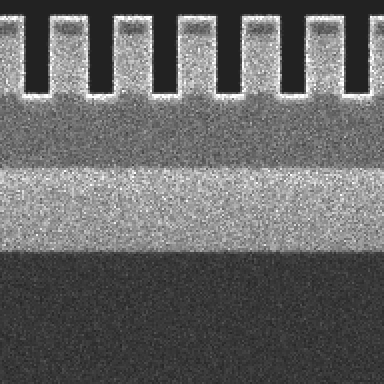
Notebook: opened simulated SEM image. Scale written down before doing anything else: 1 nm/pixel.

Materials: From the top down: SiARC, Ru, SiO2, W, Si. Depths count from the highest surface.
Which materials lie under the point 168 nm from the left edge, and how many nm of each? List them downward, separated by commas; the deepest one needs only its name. empty 78, SiO2 74, W 84, Si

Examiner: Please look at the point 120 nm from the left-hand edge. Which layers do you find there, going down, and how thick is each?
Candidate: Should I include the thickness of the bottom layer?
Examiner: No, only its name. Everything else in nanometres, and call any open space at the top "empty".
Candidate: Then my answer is SiARC 18, Ru 60, SiO2 74, W 84, Si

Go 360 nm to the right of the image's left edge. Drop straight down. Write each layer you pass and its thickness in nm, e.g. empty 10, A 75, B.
empty 78, SiO2 74, W 84, Si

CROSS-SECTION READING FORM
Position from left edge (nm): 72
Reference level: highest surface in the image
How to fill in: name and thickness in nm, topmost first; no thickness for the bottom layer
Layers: SiARC 18, Ru 60, SiO2 74, W 84, Si